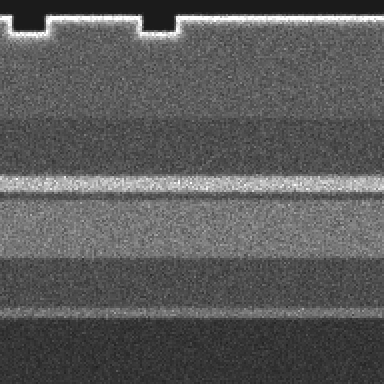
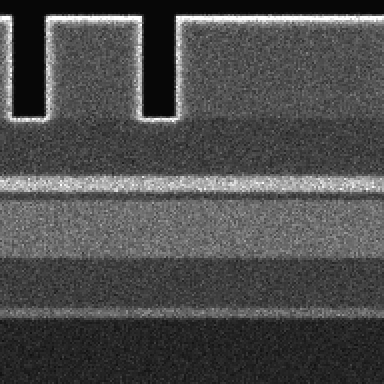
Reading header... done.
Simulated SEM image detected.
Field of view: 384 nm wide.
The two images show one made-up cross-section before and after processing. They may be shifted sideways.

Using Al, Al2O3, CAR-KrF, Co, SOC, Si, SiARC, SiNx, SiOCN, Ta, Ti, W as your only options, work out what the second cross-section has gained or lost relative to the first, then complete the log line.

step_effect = removed SOC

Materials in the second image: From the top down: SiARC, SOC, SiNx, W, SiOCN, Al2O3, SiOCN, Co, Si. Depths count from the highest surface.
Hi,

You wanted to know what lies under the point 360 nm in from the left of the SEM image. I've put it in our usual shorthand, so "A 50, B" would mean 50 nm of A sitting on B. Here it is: SiARC 16, SOC 86, SiNx 58, W 16, SiOCN 8, Al2O3 58, SiOCN 50, Co 10, Si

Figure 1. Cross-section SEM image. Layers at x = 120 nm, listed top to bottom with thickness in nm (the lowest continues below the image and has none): SiARC 16, SOC 86, SiNx 58, W 16, SiOCN 8, Al2O3 58, SiOCN 50, Co 10, Si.